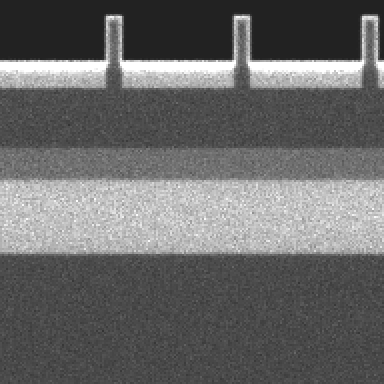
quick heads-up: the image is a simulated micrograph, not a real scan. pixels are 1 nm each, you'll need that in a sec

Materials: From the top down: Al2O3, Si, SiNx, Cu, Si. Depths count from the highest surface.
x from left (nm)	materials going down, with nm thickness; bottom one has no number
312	empty 46, Al2O3 26, Si 60, SiNx 32, Cu 74, Si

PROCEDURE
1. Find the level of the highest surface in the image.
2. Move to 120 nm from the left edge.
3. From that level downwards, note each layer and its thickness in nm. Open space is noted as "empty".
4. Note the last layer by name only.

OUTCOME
Si 132, SiNx 32, Cu 74, Si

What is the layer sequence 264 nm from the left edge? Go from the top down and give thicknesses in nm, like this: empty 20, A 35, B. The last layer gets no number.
empty 46, Al2O3 26, Si 60, SiNx 32, Cu 74, Si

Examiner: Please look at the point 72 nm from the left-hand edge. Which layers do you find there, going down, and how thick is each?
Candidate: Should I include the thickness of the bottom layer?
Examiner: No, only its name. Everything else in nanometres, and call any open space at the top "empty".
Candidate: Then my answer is empty 46, Al2O3 26, Si 60, SiNx 32, Cu 74, Si